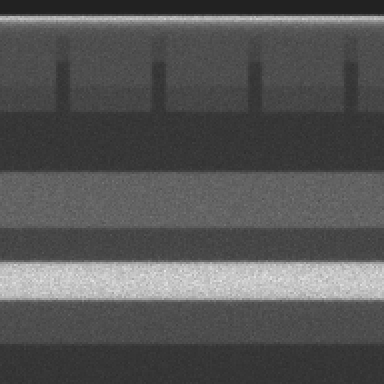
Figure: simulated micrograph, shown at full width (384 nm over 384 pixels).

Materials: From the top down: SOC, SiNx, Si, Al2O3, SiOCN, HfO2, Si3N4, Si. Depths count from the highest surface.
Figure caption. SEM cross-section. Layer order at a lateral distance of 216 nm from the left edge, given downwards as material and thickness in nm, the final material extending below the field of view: SOC 70, SiNx 26, Si 60, Al2O3 56, SiOCN 34, HfO2 38, Si3N4 44, Si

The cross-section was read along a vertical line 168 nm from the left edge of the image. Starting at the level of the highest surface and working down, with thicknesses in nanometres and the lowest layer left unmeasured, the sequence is SOC 70, SiNx 26, Si 60, Al2O3 56, SiOCN 34, HfO2 38, Si3N4 44, Si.